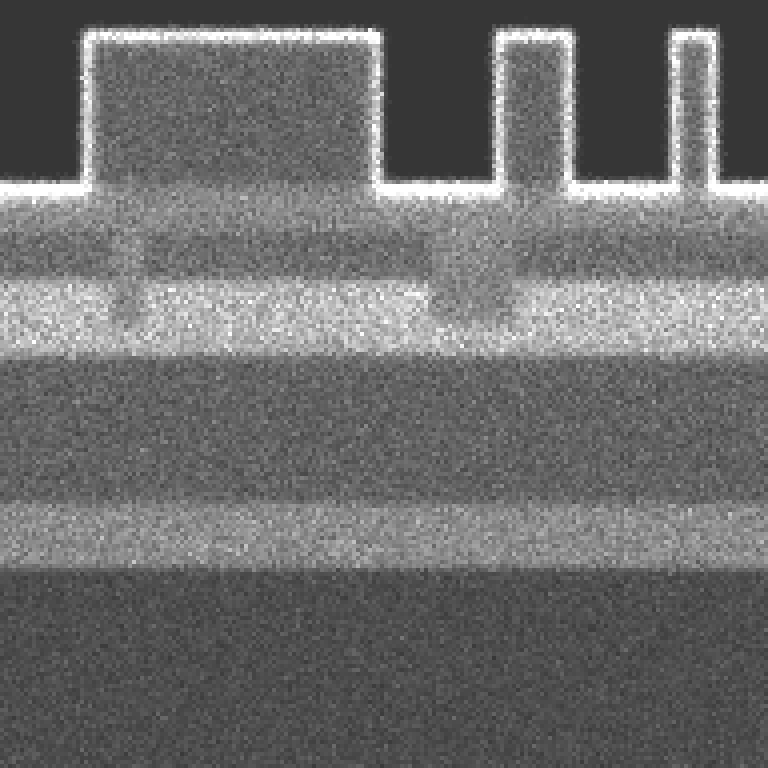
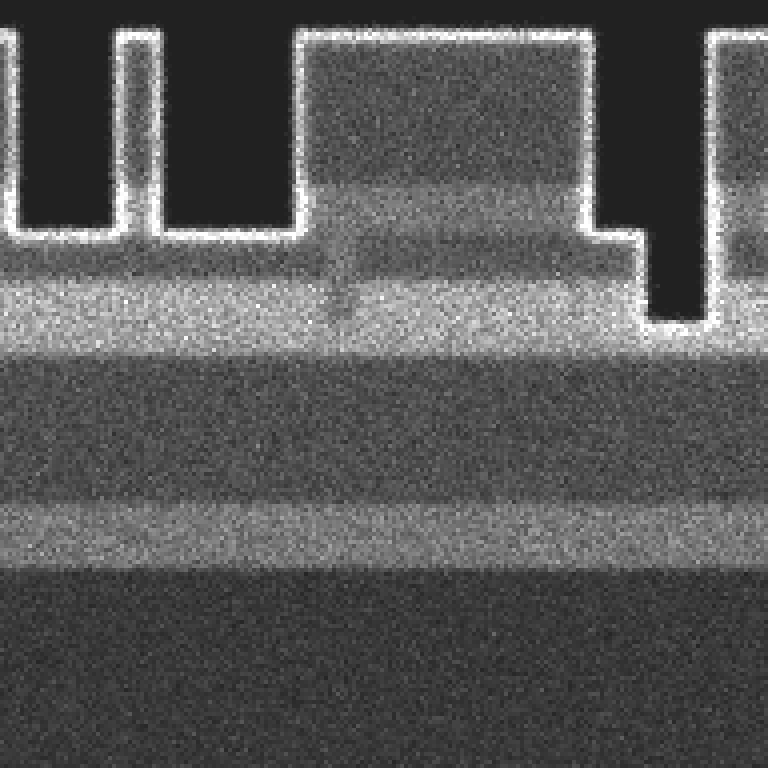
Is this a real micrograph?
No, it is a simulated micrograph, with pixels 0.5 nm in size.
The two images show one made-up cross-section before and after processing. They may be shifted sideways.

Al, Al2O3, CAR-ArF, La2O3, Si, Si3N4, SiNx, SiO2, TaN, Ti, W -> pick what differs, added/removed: SiO2 removed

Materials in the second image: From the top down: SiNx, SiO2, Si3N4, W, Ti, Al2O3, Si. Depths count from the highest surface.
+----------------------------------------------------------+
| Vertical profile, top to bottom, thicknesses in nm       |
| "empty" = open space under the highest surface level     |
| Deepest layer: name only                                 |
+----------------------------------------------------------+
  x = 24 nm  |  empty 100, Si3N4 24, W 38, Ti 74, Al2O3 32, Si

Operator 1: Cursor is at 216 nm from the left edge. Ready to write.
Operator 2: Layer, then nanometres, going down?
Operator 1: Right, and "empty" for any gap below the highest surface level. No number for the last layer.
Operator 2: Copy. SiNx 76, SiO2 24, Si3N4 24, W 38, Ti 74, Al2O3 32, Si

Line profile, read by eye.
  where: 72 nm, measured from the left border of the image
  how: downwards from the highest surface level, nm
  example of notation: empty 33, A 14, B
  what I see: SiNx 76, SiO2 24, Si3N4 24, W 38, Ti 74, Al2O3 32, Si